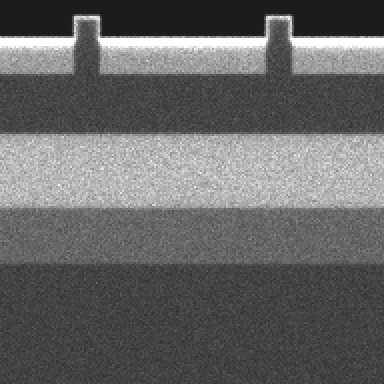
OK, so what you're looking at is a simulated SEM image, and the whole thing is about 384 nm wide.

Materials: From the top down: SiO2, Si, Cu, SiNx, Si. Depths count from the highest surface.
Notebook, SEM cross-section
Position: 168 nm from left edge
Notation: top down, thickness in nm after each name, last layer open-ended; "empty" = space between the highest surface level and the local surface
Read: empty 22, SiO2 36, Si 60, Cu 74, SiNx 56, Si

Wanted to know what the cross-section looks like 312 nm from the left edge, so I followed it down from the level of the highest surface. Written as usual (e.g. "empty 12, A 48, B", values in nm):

empty 22, SiO2 36, Si 60, Cu 74, SiNx 56, Si